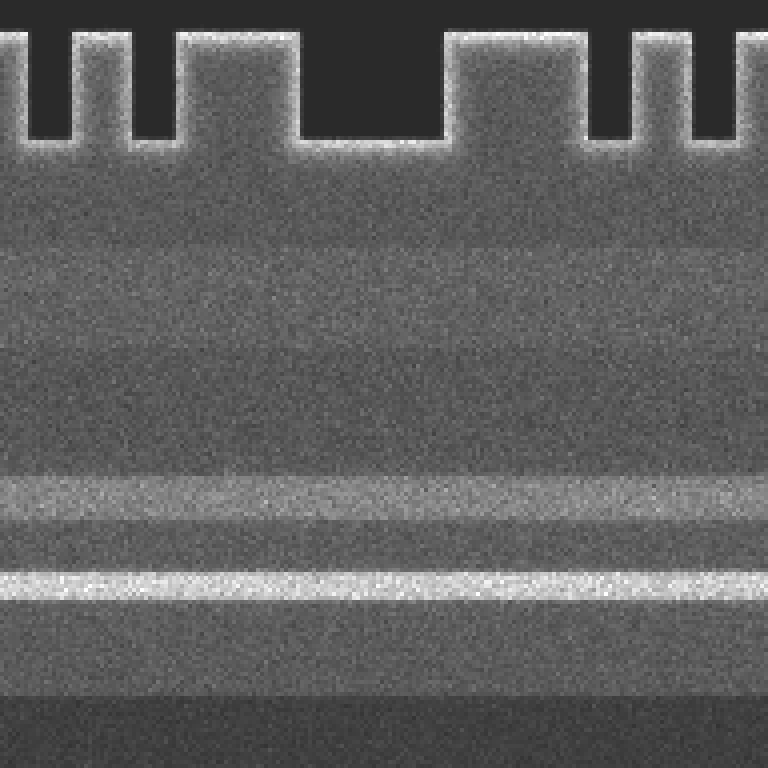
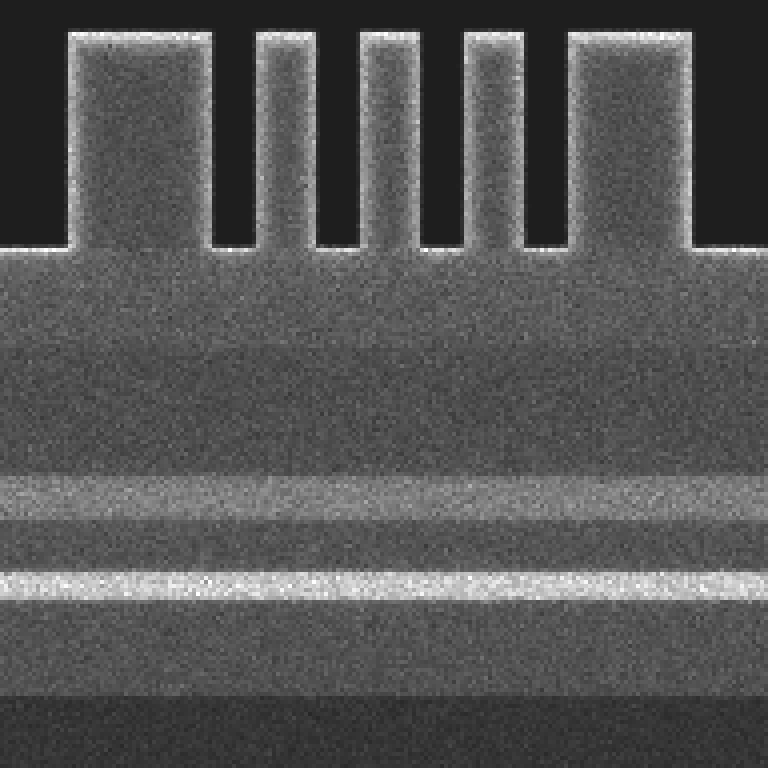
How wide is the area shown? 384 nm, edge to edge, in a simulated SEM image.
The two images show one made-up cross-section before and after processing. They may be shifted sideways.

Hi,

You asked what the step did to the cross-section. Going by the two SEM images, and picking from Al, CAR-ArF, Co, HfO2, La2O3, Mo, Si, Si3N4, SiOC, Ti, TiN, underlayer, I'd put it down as underlayer, removed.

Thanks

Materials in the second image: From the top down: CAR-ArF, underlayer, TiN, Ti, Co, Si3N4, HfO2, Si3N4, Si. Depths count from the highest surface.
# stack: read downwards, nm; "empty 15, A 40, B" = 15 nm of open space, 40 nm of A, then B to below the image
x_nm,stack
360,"empty 108, TiN 50, Ti 64, Co 22, Si3N4 26, HfO2 14, Si3N4 48, Si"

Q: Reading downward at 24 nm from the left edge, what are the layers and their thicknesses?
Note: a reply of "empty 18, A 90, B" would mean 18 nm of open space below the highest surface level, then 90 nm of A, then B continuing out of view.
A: empty 108, TiN 50, Ti 64, Co 22, Si3N4 26, HfO2 14, Si3N4 48, Si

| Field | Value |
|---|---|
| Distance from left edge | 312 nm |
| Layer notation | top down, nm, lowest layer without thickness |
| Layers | CAR-ArF 54, underlayer 54, TiN 50, Ti 64, Co 22, Si3N4 26, HfO2 14, Si3N4 48, Si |